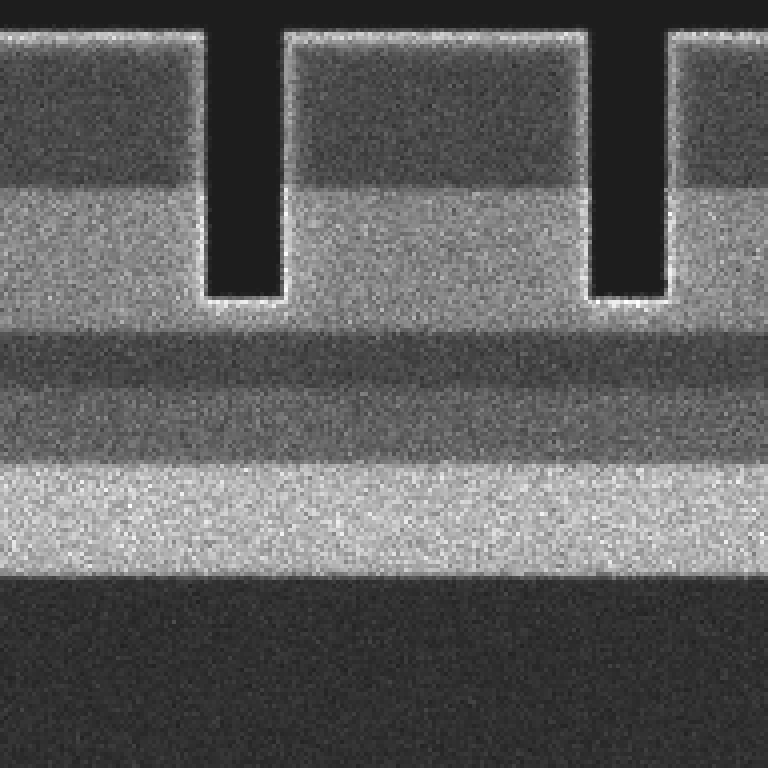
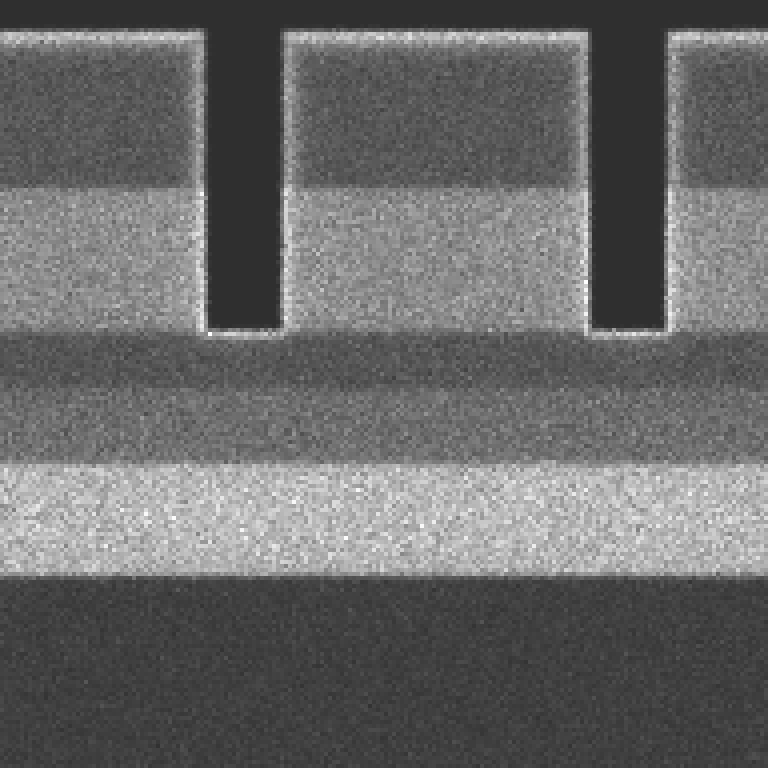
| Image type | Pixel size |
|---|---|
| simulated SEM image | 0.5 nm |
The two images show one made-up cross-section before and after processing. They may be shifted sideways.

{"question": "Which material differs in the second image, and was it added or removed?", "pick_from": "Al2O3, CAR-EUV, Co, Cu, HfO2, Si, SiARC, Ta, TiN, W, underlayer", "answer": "W, removed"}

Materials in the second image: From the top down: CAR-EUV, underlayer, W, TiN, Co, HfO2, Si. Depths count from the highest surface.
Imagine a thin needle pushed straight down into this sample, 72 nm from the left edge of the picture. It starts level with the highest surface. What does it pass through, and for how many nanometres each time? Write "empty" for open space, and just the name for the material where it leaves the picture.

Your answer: CAR-EUV 32, underlayer 46, W 72, TiN 28, Co 38, HfO2 56, Si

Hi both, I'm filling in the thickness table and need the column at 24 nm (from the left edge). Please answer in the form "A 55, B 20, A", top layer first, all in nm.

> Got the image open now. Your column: CAR-EUV 32, underlayer 46, W 72, TiN 28, Co 38, HfO2 56, Si